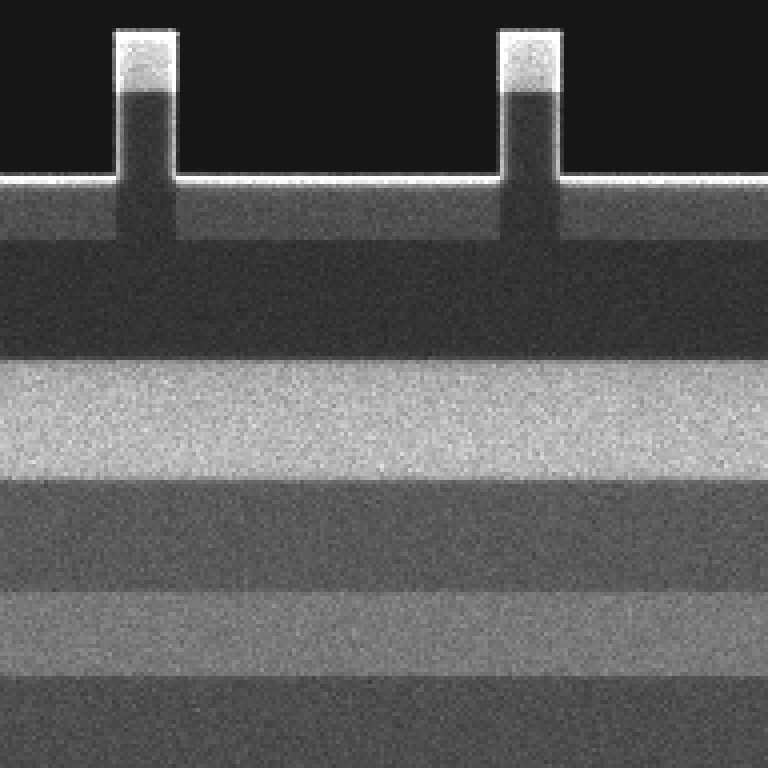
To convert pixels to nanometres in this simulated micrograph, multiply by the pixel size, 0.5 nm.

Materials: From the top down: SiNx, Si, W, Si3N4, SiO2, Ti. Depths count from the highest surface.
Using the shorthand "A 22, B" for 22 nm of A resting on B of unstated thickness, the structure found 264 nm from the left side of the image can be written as W 30, Si 134, W 60, Si3N4 56, SiO2 42, Ti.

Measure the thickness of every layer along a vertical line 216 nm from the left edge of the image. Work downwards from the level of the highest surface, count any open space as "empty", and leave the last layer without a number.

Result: empty 72, SiNx 32, Si 60, W 60, Si3N4 56, SiO2 42, Ti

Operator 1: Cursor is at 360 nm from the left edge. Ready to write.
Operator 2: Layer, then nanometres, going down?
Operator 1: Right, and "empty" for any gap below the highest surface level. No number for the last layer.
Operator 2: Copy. empty 72, SiNx 32, Si 60, W 60, Si3N4 56, SiO2 42, Ti